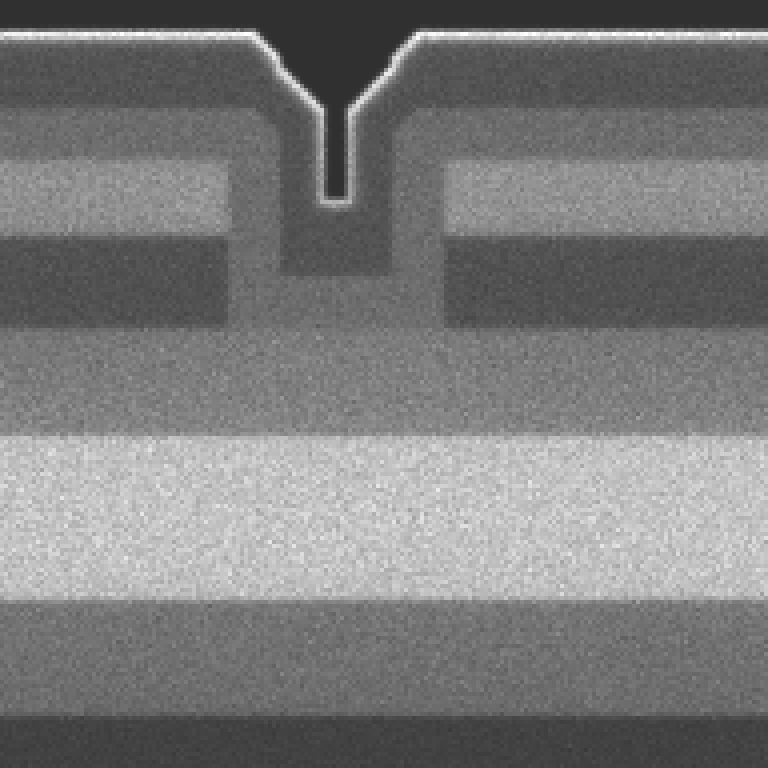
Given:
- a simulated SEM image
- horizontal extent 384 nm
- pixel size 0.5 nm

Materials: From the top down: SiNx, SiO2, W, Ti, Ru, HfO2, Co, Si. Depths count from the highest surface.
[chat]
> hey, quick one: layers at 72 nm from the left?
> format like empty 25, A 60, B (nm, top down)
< SiNx 38, SiO2 26, W 38, Ti 46, Ru 54, HfO2 82, Co 58, Si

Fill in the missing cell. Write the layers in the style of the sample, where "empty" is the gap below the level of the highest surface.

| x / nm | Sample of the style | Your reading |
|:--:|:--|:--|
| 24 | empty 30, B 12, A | SiNx 38, SiO2 26, W 38, Ti 46, Ru 54, HfO2 82, Co 58, Si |